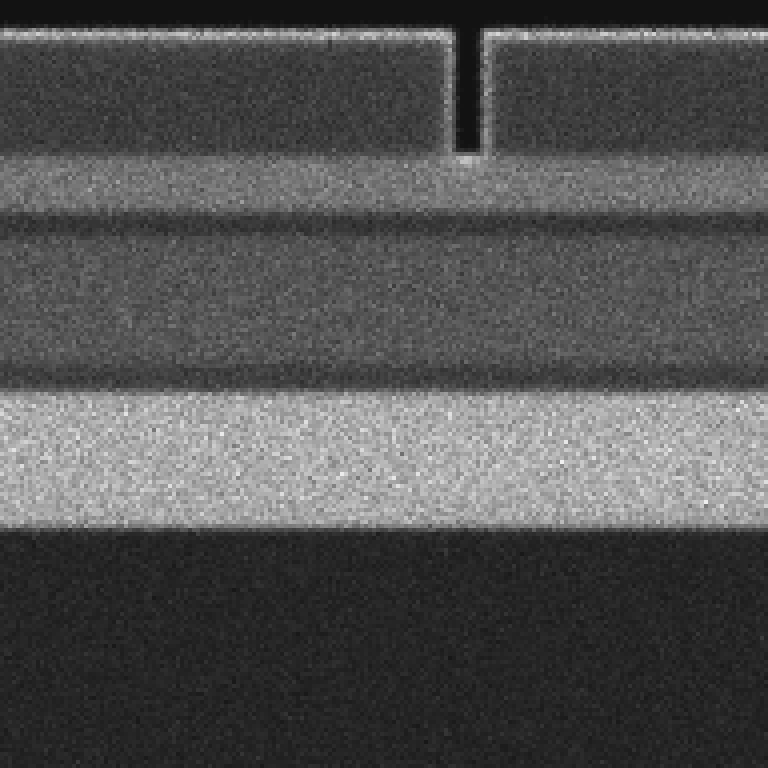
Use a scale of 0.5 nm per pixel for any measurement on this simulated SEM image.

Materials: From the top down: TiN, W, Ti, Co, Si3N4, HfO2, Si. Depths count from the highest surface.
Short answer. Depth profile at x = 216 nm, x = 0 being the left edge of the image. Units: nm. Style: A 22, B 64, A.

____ TiN 62, W 28, Ti 12, Co 64, Si3N4 14, HfO2 68, Si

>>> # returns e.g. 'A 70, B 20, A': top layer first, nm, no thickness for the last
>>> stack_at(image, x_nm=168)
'TiN 62, W 28, Ti 12, Co 64, Si3N4 14, HfO2 68, Si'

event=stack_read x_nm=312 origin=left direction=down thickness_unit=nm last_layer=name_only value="TiN 62, W 28, Ti 12, Co 64, Si3N4 14, HfO2 68, Si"